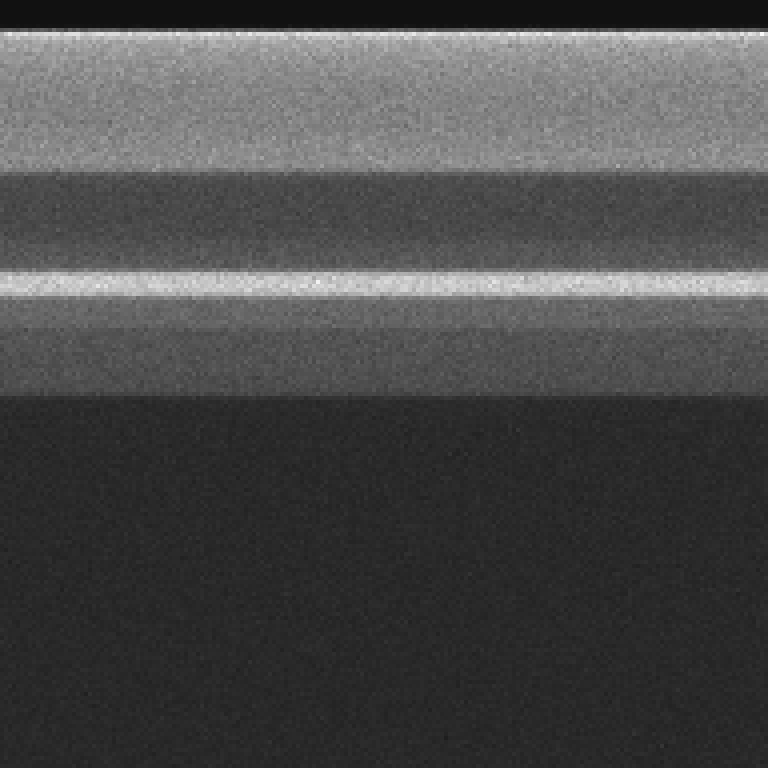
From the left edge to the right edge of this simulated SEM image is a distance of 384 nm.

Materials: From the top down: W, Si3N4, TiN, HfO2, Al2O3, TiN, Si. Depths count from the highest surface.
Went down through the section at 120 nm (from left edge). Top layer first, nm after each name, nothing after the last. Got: W 70, Si3N4 34, TiN 16, HfO2 12, Al2O3 16, TiN 34, Si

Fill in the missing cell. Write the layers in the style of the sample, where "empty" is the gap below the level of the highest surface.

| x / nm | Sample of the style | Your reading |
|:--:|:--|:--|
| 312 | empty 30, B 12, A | W 70, Si3N4 34, TiN 16, HfO2 12, Al2O3 16, TiN 34, Si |